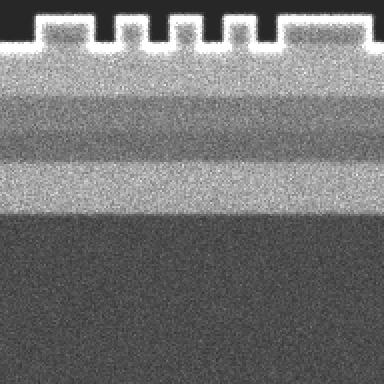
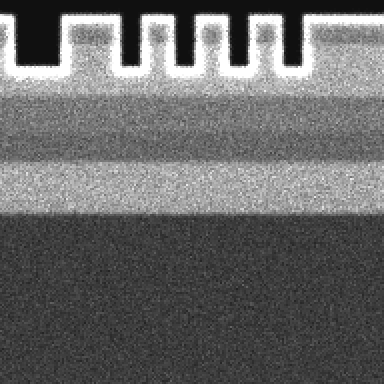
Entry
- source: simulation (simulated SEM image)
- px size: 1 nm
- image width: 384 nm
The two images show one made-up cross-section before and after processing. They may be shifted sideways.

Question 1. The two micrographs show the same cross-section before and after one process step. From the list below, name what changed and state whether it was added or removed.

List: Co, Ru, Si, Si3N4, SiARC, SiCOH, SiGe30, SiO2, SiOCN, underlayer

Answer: SiO2, removed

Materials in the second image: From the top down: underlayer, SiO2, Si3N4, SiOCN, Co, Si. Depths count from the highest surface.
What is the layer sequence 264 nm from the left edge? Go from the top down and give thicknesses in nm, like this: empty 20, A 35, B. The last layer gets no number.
underlayer 28, SiO2 52, Si3N4 36, SiOCN 30, Co 52, Si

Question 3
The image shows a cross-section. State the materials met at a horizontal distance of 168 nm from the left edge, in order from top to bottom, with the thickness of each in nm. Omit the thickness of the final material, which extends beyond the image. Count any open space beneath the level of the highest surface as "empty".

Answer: underlayer 28, SiO2 52, Si3N4 36, SiOCN 30, Co 52, Si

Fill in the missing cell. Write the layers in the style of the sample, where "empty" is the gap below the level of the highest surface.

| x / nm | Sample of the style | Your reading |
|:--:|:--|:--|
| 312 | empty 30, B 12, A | underlayer 28, SiO2 52, Si3N4 36, SiOCN 30, Co 52, Si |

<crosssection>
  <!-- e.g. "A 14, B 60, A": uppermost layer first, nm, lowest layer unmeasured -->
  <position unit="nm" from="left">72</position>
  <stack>underlayer 28, SiO2 52, Si3N4 36, SiOCN 30, Co 52, Si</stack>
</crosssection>